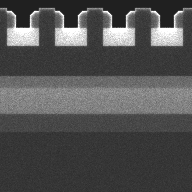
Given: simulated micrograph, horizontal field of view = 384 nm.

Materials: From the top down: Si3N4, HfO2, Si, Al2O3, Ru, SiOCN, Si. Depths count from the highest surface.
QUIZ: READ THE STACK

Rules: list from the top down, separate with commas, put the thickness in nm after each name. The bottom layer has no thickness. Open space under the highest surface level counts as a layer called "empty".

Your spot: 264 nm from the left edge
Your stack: empty 6, Si3N4 34, HfO2 36, Si 60, Al2O3 24, Ru 52, SiOCN 36, Si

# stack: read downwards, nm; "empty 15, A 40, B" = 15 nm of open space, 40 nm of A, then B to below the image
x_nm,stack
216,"empty 8, Si3N4 32, HfO2 36, Si 60, Al2O3 24, Ru 52, SiOCN 36, Si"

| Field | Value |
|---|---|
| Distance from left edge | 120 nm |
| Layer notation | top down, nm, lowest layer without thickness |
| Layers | empty 8, Si3N4 32, HfO2 36, Si 60, Al2O3 24, Ru 52, SiOCN 36, Si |